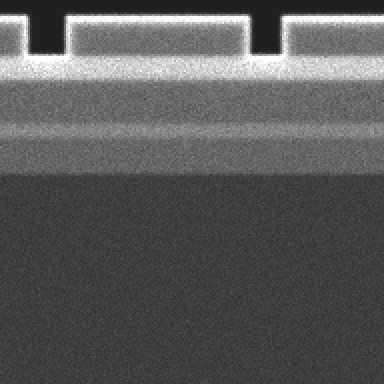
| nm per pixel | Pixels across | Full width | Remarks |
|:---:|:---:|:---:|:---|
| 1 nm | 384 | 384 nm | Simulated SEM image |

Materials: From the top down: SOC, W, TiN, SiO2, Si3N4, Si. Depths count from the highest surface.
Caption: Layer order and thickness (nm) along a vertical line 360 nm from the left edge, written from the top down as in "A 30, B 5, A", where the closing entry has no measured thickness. SOC 40, W 24, TiN 44, SiO2 14, Si3N4 36, Si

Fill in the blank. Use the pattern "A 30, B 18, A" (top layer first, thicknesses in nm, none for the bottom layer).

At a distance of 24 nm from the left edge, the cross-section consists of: SOC 40, W 24, TiN 44, SiO2 14, Si3N4 36, Si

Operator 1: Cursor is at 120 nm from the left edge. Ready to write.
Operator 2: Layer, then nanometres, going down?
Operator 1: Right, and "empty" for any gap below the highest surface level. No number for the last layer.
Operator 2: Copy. SOC 40, W 24, TiN 44, SiO2 14, Si3N4 36, Si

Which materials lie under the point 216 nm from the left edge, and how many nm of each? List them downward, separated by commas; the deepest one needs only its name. SOC 40, W 24, TiN 44, SiO2 14, Si3N4 36, Si